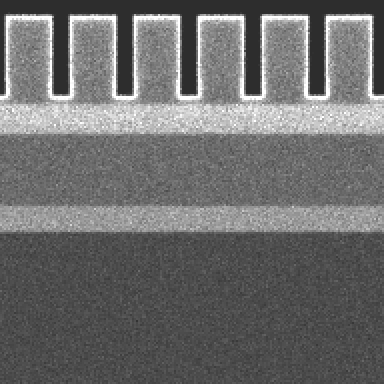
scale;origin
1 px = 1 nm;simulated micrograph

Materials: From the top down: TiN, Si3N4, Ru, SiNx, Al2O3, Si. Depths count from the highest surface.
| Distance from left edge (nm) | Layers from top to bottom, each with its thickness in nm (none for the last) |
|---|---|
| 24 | TiN 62, Si3N4 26, Ru 30, SiNx 72, Al2O3 26, Si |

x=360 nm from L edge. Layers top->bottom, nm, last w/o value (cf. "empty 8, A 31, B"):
TiN 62, Si3N4 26, Ru 30, SiNx 72, Al2O3 26, Si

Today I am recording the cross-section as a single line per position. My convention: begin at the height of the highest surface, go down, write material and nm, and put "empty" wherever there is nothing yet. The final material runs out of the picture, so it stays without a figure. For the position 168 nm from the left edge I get TiN 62, Si3N4 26, Ru 30, SiNx 72, Al2O3 26, Si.